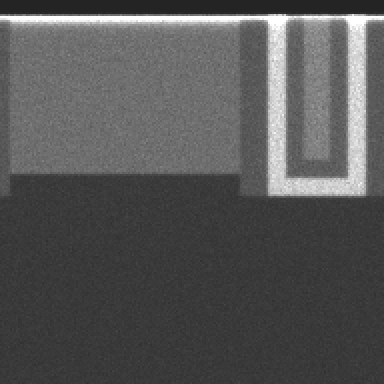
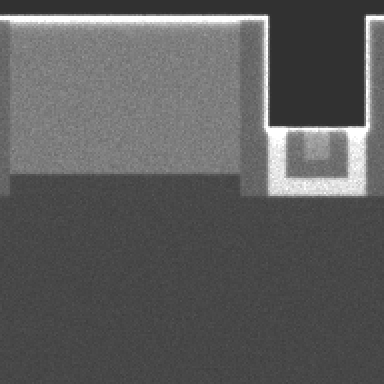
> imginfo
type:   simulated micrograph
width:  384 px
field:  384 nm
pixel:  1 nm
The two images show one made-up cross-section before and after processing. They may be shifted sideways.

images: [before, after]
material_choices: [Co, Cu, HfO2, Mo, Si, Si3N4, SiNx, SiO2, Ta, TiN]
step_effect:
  removed: Co and HfO2 and TiN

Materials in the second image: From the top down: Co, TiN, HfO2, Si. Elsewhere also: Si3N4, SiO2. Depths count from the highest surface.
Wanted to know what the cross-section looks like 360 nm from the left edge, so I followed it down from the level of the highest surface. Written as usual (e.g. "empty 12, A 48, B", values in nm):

empty 112, HfO2 68, Si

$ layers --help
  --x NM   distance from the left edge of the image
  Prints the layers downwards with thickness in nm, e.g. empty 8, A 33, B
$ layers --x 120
SiO2 158, Si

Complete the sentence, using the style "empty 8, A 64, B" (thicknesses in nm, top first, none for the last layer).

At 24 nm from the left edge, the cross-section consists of SiO2 158, Si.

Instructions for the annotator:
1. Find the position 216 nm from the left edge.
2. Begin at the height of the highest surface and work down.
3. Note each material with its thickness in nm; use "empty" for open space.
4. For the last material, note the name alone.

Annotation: SiO2 158, Si